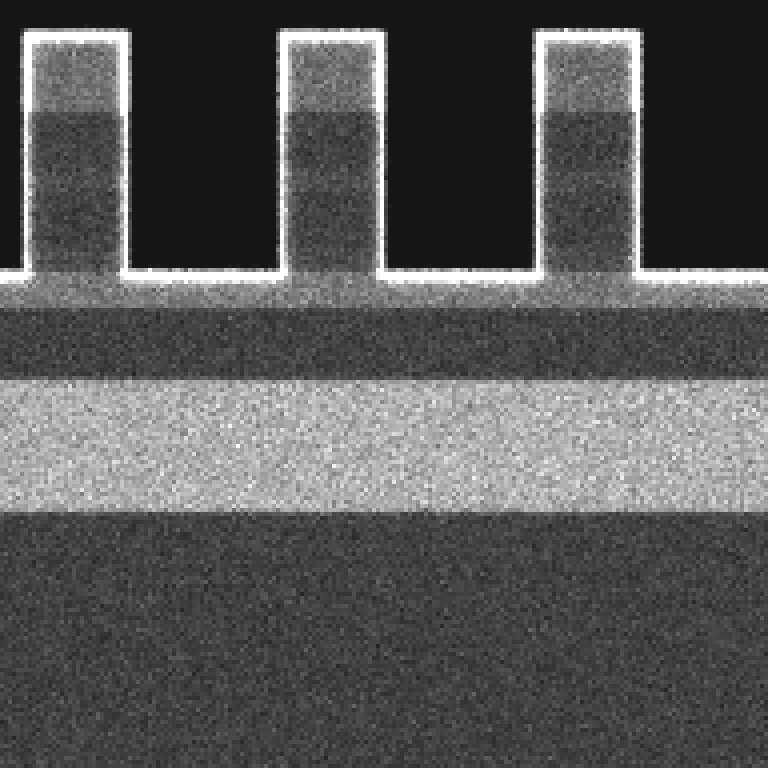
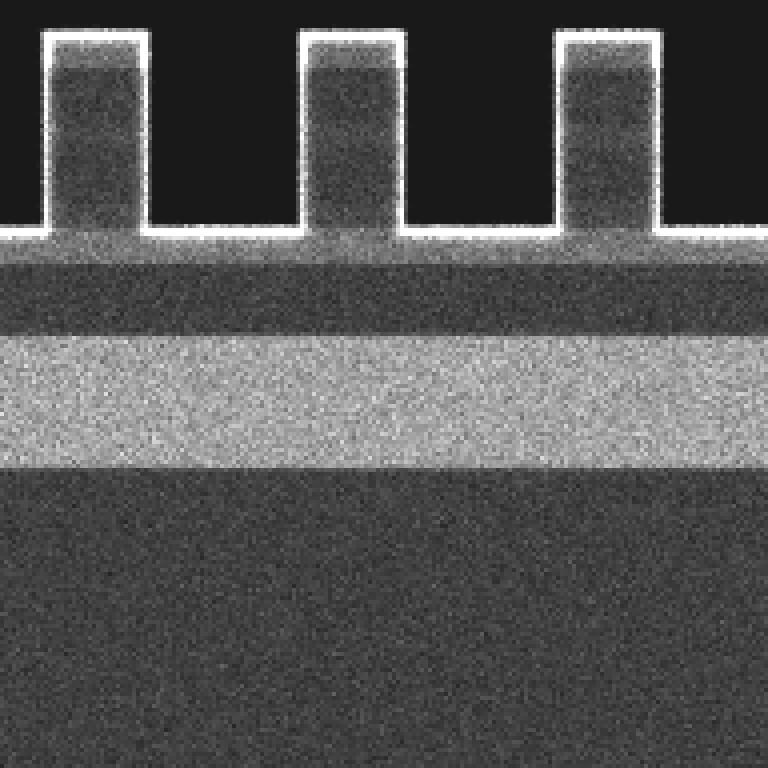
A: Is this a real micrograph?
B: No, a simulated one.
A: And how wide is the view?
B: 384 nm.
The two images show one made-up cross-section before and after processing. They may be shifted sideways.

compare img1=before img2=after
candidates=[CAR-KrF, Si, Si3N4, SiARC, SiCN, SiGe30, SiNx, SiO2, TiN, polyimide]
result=removed:SiNx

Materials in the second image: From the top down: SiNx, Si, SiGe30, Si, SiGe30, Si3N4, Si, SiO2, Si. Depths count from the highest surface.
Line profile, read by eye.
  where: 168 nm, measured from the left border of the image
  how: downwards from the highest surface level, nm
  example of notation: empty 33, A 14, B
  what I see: SiNx 18, Si 28, SiGe30 12, Si 28, SiGe30 12, Si3N4 18, Si 36, SiO2 66, Si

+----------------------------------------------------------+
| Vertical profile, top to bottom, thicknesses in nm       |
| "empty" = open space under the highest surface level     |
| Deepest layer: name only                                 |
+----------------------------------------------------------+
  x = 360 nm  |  empty 98, Si3N4 18, Si 36, SiO2 66, Si